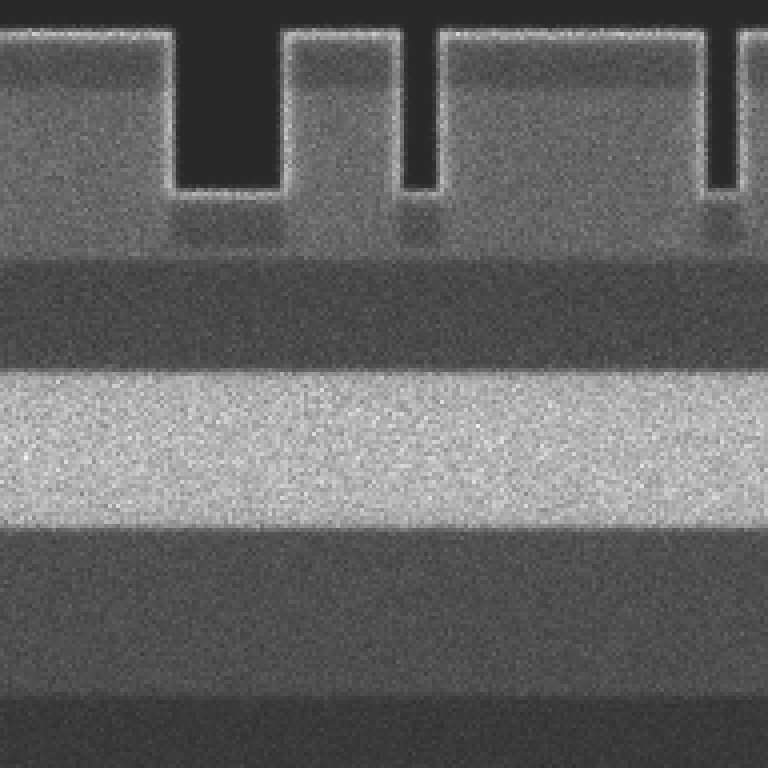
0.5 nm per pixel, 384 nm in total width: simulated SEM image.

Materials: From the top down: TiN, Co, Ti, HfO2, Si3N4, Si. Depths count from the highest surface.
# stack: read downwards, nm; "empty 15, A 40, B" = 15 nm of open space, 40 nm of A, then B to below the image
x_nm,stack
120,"empty 80, TiN 28, Co 6, Ti 56, HfO2 78, Si3N4 84, Si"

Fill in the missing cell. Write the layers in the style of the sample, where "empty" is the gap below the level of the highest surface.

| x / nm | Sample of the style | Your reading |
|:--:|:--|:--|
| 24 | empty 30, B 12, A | TiN 28, Co 86, Ti 56, HfO2 78, Si3N4 84, Si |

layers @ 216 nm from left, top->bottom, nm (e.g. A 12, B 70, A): empty 80, TiN 28, Co 6, Ti 56, HfO2 78, Si3N4 84, Si